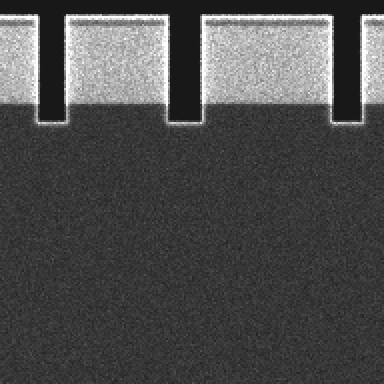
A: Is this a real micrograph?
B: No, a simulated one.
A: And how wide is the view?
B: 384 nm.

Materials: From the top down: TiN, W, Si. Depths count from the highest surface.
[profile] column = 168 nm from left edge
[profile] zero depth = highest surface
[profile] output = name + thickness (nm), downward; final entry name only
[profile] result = empty 106, Si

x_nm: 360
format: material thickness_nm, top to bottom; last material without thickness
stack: empty 106, Si